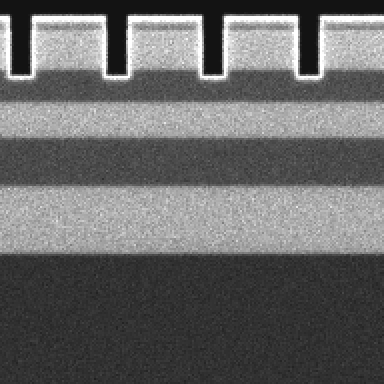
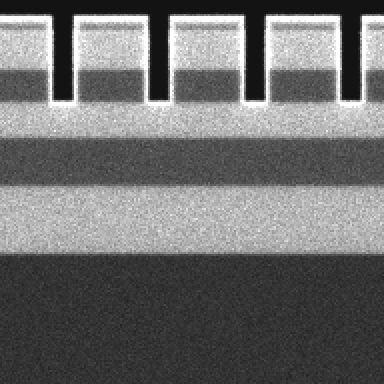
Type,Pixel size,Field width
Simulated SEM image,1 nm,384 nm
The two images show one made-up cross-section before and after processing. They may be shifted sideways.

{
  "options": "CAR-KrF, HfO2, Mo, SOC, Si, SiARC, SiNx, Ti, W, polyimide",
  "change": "removed",
  "material": "SiNx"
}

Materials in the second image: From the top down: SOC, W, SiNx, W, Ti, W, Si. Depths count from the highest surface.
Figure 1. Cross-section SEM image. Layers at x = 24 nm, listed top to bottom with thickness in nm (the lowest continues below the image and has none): SOC 14, W 40, SiNx 32, W 36, Ti 48, W 68, Si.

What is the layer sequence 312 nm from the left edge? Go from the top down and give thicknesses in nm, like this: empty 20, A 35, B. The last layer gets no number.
SOC 14, W 40, SiNx 32, W 36, Ti 48, W 68, Si